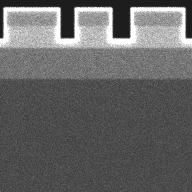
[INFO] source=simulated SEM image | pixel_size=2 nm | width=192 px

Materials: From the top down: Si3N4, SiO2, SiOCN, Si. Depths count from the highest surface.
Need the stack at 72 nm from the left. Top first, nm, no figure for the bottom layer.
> Si3N4 36, SiO2 44, SiOCN 62, Si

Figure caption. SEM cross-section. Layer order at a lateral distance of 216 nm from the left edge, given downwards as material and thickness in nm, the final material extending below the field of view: Si3N4 36, SiO2 44, SiOCN 62, Si